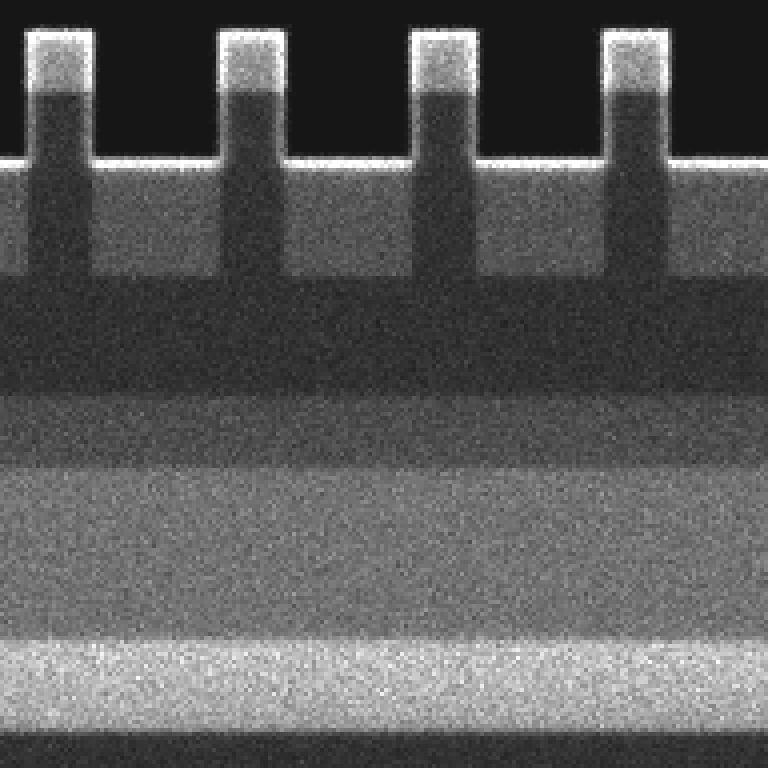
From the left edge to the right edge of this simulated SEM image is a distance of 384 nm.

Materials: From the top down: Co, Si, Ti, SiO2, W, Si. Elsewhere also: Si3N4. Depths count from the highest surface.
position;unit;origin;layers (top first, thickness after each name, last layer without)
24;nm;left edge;Co 30, Si 152, Ti 36, SiO2 86, W 46, Si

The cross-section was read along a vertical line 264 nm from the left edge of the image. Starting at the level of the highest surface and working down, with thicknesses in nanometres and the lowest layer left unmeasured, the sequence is empty 64, Si3N4 58, Si 60, Ti 36, SiO2 86, W 46, Si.